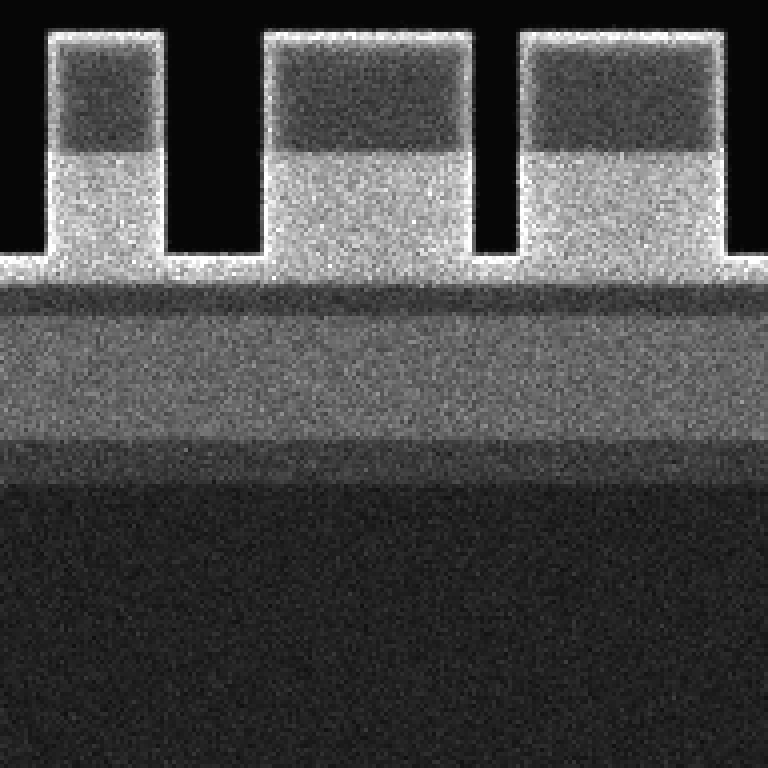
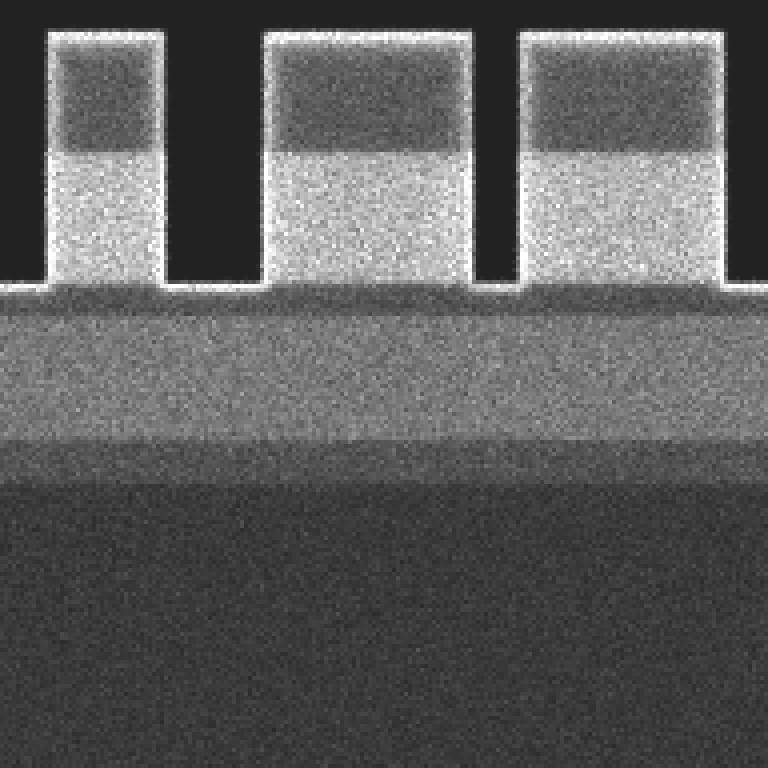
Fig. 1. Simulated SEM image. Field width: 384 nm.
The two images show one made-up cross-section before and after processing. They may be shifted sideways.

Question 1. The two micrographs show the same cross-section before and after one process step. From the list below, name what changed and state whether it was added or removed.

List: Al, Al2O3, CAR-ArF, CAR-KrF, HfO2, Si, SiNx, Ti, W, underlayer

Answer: W, removed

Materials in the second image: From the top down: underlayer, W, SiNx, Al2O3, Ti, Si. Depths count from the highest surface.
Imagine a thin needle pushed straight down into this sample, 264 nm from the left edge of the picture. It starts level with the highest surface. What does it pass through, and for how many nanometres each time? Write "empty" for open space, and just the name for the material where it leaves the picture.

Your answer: underlayer 60, W 66, SiNx 16, Al2O3 62, Ti 22, Si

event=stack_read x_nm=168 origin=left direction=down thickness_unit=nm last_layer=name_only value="underlayer 60, W 66, SiNx 16, Al2O3 62, Ti 22, Si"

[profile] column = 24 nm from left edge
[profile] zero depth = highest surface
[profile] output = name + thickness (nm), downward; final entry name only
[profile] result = underlayer 60, W 66, SiNx 16, Al2O3 62, Ti 22, Si